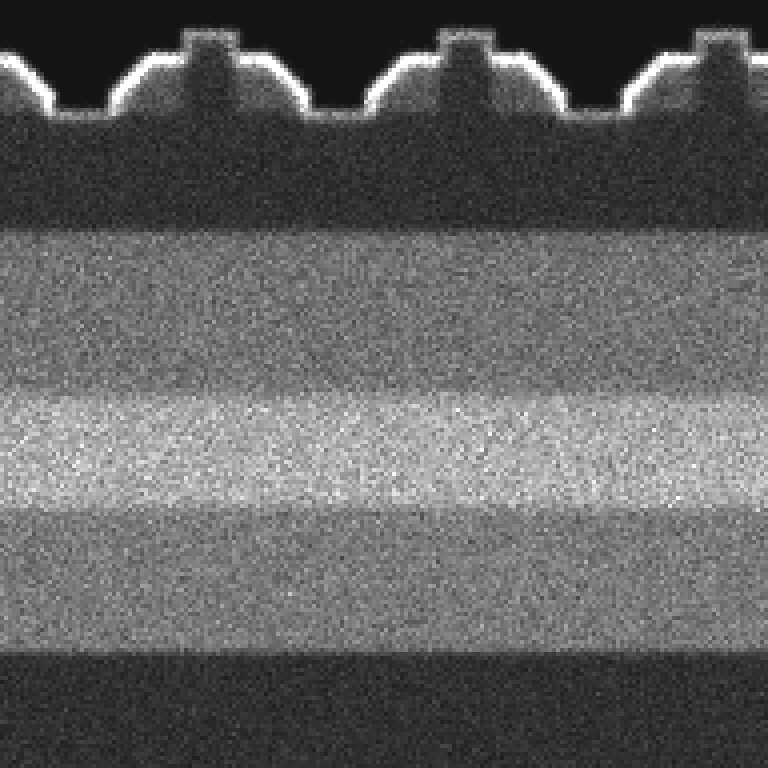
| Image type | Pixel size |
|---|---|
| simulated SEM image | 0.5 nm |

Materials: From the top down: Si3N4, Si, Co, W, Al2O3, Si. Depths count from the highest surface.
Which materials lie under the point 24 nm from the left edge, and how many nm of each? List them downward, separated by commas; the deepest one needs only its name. empty 30, Si3N4 10, Si 60, Co 82, W 56, Al2O3 72, Si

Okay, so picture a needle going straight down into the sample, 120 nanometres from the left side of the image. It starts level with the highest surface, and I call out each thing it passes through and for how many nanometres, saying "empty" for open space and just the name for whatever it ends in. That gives empty 12, Si3N4 28, Si 60, Co 82, W 56, Al2O3 72, Si